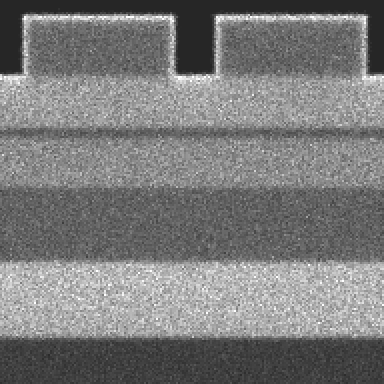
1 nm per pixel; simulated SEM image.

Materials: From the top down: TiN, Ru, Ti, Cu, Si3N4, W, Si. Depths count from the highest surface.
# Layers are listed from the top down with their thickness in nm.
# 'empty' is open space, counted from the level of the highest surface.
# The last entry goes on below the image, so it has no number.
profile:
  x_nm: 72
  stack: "TiN 60, Ru 52, Ti 10, Cu 50, Si3N4 74, W 76, Si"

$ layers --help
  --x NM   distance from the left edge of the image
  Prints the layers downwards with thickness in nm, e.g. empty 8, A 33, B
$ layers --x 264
TiN 60, Ru 52, Ti 10, Cu 50, Si3N4 74, W 76, Si